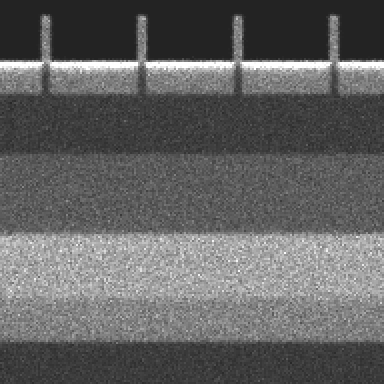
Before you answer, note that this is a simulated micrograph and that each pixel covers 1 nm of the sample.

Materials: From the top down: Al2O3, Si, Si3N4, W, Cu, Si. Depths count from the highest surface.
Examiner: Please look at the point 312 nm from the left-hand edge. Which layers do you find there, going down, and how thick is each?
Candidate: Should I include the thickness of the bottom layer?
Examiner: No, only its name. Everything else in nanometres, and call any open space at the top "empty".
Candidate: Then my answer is empty 46, Al2O3 32, Si 60, Si3N4 80, W 64, Cu 44, Si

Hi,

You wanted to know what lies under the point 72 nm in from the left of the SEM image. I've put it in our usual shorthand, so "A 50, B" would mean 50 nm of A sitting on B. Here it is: empty 46, Al2O3 32, Si 60, Si3N4 80, W 64, Cu 44, Si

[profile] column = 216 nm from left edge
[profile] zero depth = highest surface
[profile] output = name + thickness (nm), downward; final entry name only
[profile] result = empty 46, Al2O3 32, Si 60, Si3N4 80, W 64, Cu 44, Si